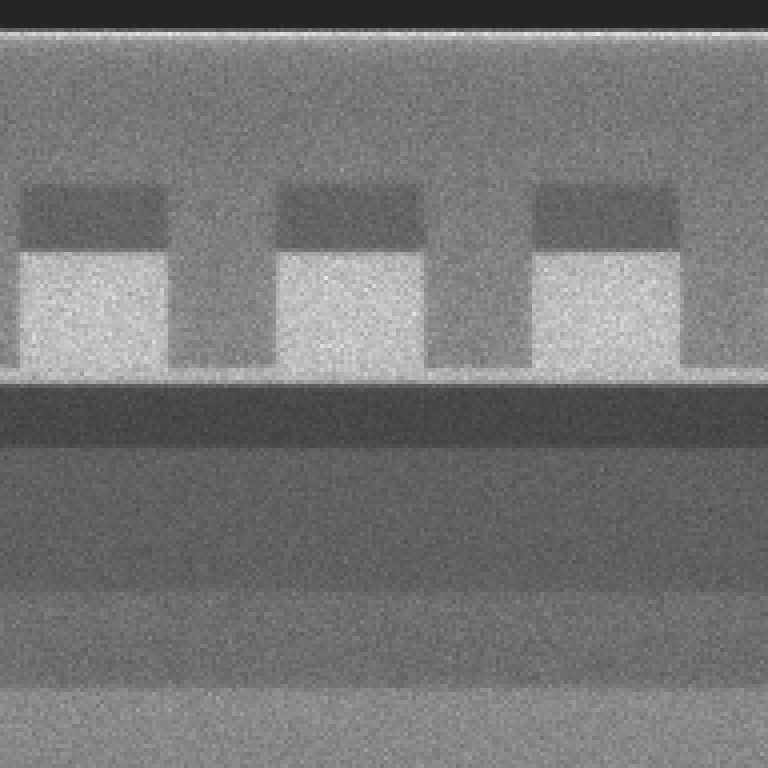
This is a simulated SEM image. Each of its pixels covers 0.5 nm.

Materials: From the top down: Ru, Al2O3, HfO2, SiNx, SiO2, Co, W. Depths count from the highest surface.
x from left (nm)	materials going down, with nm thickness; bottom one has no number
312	Ru 76, Al2O3 34, HfO2 66, SiNx 32, SiO2 72, Co 48, W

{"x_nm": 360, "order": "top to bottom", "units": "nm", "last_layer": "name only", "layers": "Ru 168, HfO2 8, SiNx 32, SiO2 72, Co 48, W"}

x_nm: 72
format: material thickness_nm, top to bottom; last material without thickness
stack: Ru 76, Al2O3 34, HfO2 66, SiNx 32, SiO2 72, Co 48, W